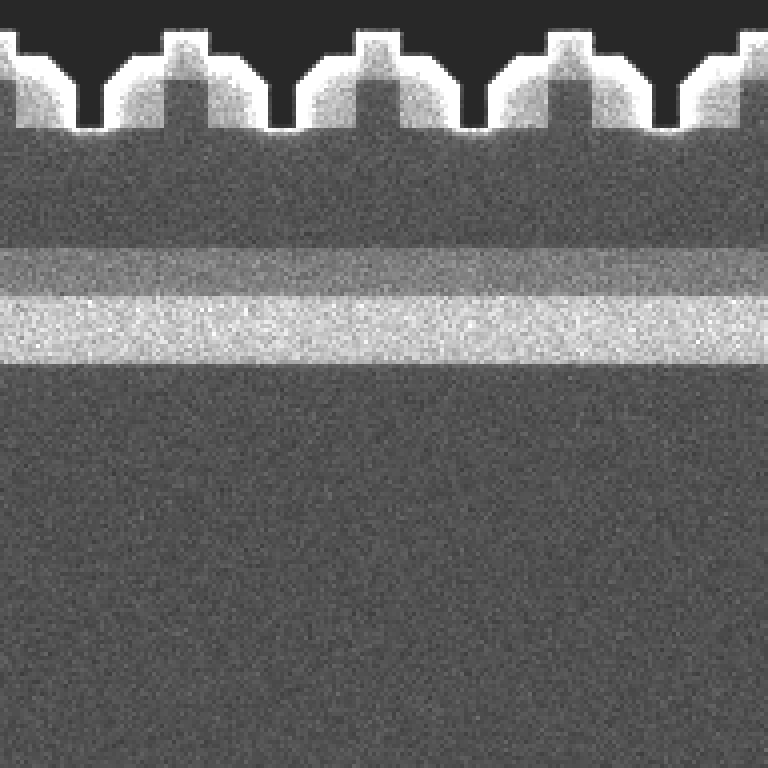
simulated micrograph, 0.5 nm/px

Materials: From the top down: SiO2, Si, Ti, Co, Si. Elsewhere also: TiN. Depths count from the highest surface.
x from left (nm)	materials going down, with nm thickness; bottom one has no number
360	empty 12, SiO2 36, Si 60, Ti 24, Co 34, Si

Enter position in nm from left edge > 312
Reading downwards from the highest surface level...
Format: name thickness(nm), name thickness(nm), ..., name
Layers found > empty 14, SiO2 34, Si 60, Ti 24, Co 34, Si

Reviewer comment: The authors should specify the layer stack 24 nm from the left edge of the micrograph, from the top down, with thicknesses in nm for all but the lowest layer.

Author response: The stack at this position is empty 14, SiO2 34, Si 60, Ti 24, Co 34, Si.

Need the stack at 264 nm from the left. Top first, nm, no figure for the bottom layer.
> empty 12, SiO2 36, Si 60, Ti 24, Co 34, Si